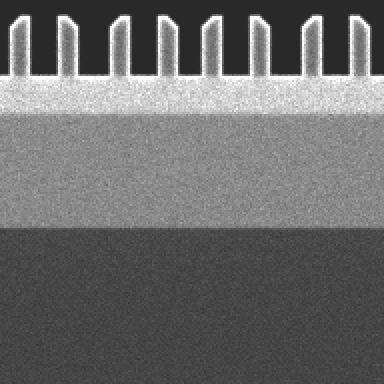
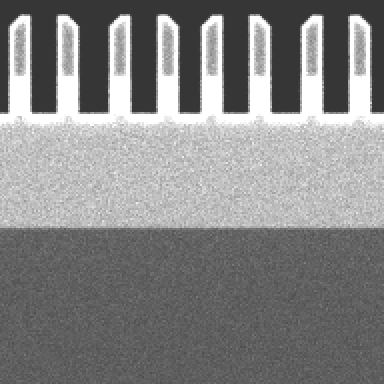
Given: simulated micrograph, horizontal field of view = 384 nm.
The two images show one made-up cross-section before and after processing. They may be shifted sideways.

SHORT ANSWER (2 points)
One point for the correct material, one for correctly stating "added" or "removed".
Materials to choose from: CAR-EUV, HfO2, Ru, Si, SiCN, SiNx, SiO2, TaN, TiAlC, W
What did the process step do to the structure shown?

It removed Ru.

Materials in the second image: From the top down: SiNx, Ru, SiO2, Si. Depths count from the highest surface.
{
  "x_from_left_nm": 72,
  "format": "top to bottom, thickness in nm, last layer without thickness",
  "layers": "empty 6, SiNx 54, Ru 38, SiO2 114, Si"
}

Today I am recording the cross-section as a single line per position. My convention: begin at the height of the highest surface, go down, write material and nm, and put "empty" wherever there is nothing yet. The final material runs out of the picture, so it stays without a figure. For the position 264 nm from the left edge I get empty 6, SiNx 54, Ru 38, SiO2 114, Si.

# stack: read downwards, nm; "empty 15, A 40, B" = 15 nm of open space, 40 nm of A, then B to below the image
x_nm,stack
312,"SiNx 60, Ru 38, SiO2 114, Si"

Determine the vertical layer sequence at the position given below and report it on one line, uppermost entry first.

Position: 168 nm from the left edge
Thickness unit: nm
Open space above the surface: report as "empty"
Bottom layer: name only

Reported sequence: empty 2, SiNx 58, Ru 38, SiO2 114, Si